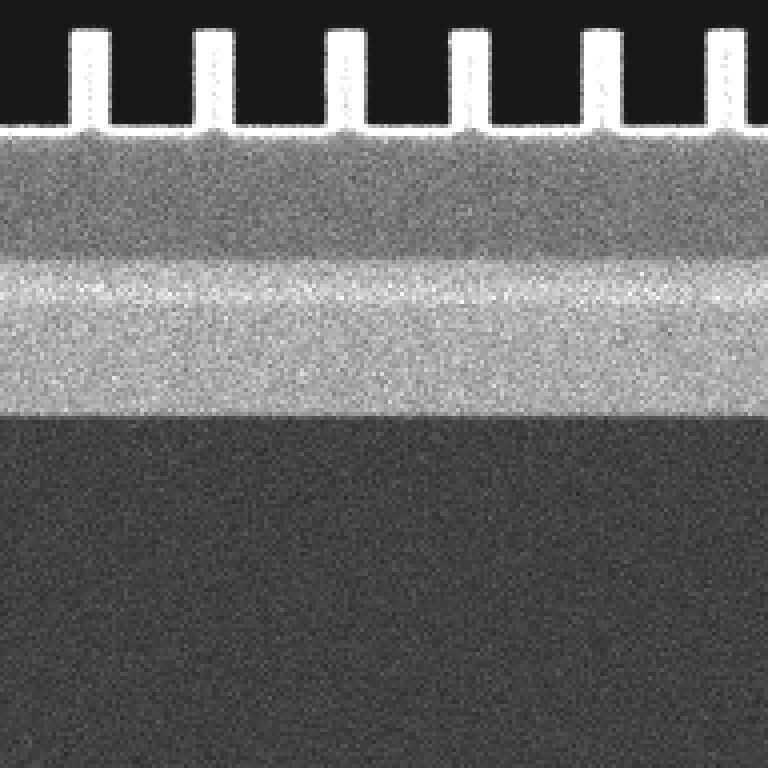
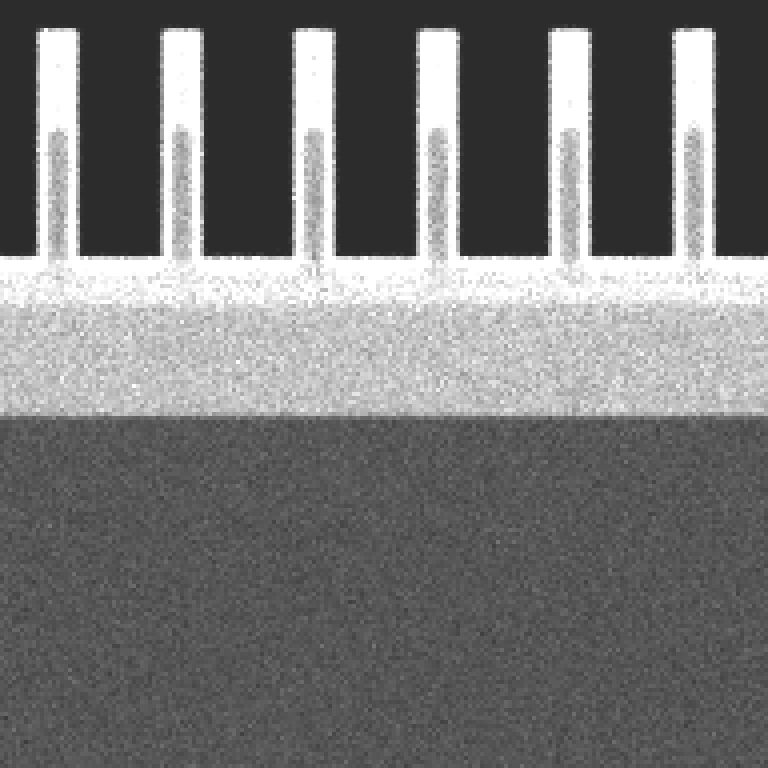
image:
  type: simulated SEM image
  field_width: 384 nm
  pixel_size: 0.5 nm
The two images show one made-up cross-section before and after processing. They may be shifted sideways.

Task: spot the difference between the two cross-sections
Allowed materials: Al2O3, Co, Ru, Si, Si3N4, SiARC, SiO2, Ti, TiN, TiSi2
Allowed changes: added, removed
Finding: removed TiN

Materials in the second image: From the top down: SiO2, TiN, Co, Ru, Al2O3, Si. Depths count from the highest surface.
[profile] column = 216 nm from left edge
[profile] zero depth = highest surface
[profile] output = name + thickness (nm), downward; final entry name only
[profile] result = SiO2 48, TiN 66, Co 12, Ru 10, Al2O3 56, Si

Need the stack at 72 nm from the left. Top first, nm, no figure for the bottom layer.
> empty 114, Co 12, Ru 10, Al2O3 56, Si